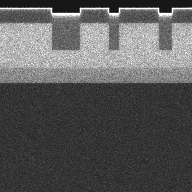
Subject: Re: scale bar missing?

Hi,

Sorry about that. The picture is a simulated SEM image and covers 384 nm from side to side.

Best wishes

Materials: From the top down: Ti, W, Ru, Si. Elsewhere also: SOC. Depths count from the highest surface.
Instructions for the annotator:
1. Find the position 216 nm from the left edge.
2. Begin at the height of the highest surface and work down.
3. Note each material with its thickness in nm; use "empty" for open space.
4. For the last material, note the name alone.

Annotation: Ti 30, W 90, Ru 30, Si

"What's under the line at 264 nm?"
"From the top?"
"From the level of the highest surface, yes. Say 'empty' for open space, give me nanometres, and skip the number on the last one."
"Ti 30, W 90, Ru 30, Si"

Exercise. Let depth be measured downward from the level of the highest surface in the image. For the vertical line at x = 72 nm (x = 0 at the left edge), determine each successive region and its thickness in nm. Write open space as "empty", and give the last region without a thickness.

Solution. Ti 30, W 90, Ru 30, Si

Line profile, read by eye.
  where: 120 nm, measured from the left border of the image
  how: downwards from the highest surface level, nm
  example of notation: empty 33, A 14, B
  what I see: empty 10, SOC 74, W 36, Ru 30, Si